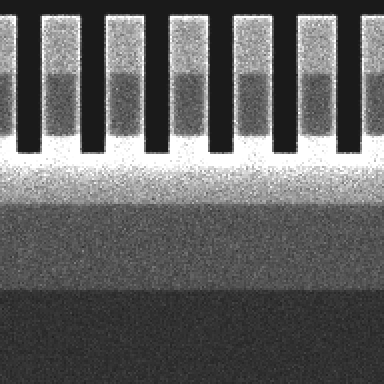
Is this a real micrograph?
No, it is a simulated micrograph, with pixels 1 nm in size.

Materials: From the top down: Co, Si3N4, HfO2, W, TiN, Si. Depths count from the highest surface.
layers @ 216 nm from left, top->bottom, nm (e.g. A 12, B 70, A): empty 138, HfO2 12, W 38, TiN 86, Si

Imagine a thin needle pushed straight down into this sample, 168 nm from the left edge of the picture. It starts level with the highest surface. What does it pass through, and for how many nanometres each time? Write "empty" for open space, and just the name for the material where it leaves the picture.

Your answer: empty 138, HfO2 12, W 38, TiN 86, Si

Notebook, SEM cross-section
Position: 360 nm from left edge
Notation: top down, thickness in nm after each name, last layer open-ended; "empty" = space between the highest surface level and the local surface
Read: empty 138, HfO2 12, W 38, TiN 86, Si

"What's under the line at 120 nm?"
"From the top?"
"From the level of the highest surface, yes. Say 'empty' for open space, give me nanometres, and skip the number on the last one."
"Co 58, Si3N4 62, HfO2 30, W 38, TiN 86, Si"